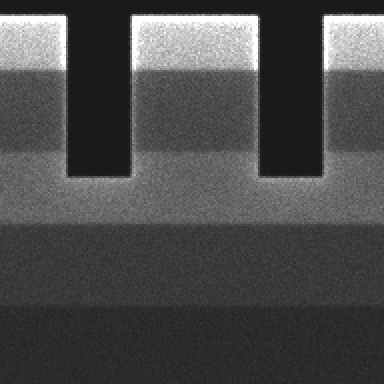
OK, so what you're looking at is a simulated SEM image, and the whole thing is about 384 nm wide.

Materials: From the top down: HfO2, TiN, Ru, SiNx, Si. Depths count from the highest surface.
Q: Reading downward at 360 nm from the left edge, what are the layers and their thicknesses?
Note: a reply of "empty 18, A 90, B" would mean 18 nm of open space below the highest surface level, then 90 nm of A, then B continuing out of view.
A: HfO2 54, TiN 82, Ru 72, SiNx 82, Si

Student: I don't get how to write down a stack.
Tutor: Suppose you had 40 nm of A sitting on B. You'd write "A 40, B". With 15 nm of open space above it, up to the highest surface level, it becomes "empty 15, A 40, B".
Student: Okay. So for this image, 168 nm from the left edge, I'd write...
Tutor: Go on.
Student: HfO2 54, TiN 82, Ru 72, SiNx 82, Si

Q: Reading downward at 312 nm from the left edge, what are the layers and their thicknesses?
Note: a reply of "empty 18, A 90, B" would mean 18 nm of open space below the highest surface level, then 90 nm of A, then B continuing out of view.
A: empty 162, Ru 46, SiNx 82, Si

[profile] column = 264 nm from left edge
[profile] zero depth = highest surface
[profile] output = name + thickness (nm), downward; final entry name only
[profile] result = empty 162, Ru 46, SiNx 82, Si